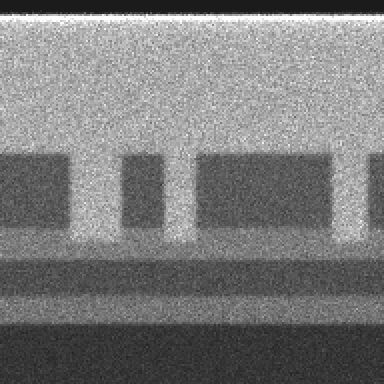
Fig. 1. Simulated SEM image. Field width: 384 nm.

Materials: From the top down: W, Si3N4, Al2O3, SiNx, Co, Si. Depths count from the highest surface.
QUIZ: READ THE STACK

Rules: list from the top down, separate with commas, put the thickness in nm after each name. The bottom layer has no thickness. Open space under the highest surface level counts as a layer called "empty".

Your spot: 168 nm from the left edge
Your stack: W 226, Al2O3 18, SiNx 36, Co 28, Si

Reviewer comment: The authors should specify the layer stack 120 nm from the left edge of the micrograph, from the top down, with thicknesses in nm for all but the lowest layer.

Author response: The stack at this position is W 226, Al2O3 18, SiNx 36, Co 28, Si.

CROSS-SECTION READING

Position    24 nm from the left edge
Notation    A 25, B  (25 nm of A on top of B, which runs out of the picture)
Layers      W 138, Si3N4 74, Al2O3 32, SiNx 36, Co 28, Si